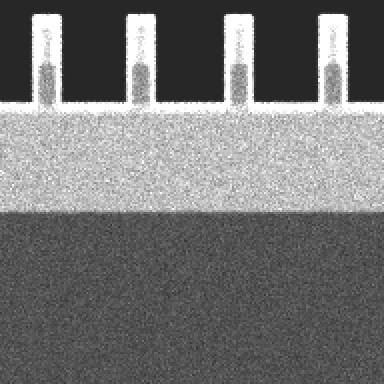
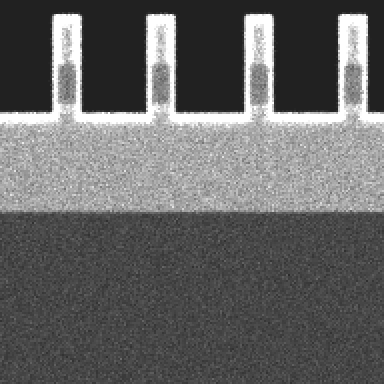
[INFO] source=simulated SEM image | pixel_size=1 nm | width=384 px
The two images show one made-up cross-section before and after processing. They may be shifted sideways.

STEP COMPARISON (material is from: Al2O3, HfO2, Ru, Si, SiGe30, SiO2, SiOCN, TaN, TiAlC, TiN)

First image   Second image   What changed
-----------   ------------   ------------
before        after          Ru, removed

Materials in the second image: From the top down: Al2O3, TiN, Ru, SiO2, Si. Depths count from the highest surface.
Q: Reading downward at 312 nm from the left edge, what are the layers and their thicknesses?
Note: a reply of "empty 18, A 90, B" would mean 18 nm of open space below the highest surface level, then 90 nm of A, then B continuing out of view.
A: empty 98, SiO2 98, Si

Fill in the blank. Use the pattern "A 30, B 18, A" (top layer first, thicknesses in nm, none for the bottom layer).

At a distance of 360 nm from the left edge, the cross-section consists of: Al2O3 48, TiN 40, Ru 10, SiO2 98, Si